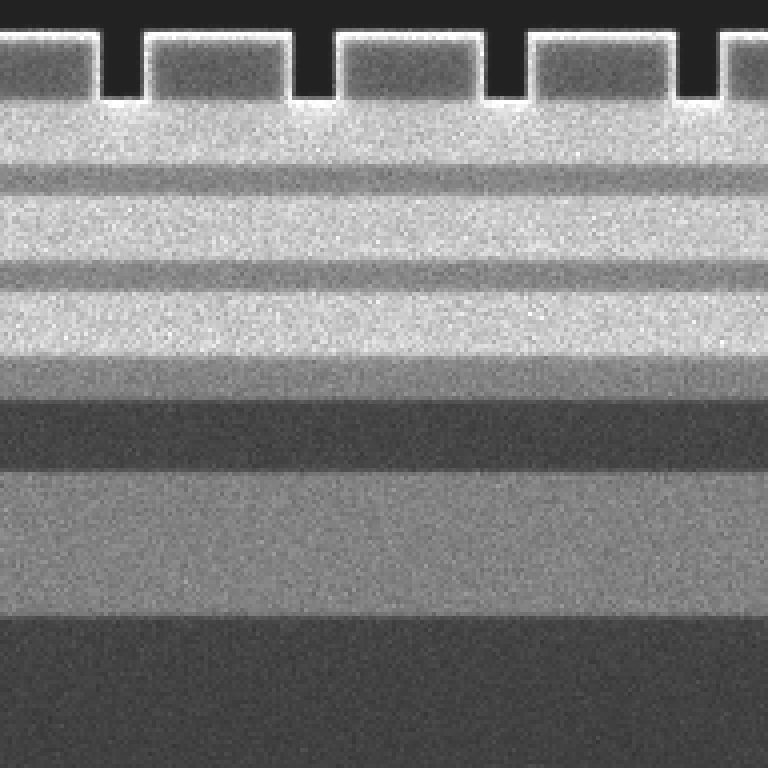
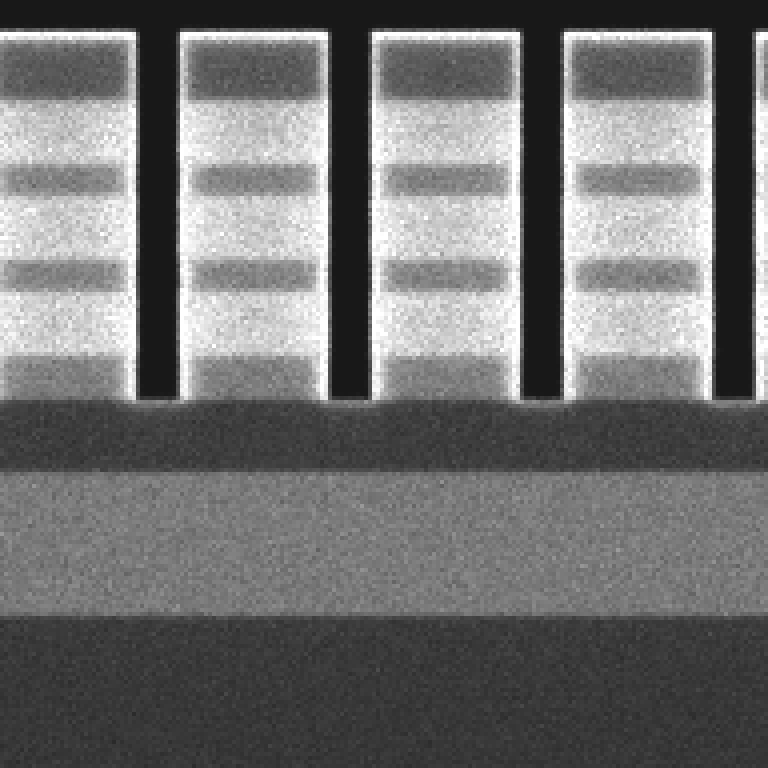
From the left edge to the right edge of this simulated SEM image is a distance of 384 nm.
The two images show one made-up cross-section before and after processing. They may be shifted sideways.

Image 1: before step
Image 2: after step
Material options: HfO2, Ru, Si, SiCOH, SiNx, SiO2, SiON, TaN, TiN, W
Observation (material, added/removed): SiO2 and W, removed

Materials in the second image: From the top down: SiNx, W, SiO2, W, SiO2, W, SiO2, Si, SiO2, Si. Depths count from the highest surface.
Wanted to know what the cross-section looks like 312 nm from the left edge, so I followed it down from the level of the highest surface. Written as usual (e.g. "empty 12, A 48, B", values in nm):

SiNx 34, W 32, SiO2 16, W 32, SiO2 16, W 32, SiO2 22, Si 36, SiO2 72, Si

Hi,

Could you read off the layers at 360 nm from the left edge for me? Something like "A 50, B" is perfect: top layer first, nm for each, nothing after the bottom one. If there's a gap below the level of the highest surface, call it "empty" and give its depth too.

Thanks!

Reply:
empty 184, Si 36, SiO2 72, Si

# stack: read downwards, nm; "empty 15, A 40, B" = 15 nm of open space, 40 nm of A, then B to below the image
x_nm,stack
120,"SiNx 34, W 32, SiO2 16, W 32, SiO2 16, W 32, SiO2 22, Si 36, SiO2 72, Si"